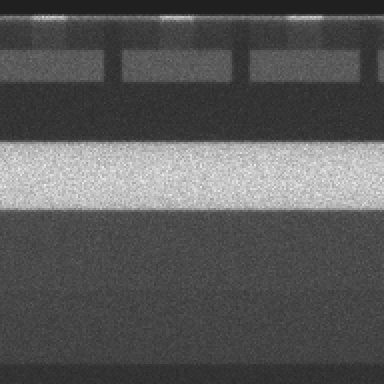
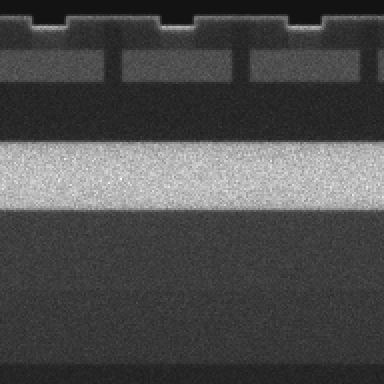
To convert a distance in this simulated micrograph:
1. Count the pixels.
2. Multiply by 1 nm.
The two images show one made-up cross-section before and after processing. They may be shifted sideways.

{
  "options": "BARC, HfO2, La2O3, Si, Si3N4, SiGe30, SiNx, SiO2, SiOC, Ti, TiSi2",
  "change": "removed",
  "material": "SiNx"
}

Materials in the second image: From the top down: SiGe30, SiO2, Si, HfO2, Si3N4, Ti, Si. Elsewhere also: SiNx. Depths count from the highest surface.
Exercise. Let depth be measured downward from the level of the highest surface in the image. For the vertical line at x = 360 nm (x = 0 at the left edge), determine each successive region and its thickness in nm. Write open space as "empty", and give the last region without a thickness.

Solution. Si 126, HfO2 68, Si3N4 80, Ti 74, Si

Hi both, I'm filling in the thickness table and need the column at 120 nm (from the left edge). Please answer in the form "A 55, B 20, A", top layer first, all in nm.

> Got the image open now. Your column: Si 126, HfO2 68, Si3N4 80, Ti 74, Si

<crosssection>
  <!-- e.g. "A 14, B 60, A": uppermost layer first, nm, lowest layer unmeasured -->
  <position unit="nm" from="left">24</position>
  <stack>SiGe30 34, SiO2 32, Si 60, HfO2 68, Si3N4 80, Ti 74, Si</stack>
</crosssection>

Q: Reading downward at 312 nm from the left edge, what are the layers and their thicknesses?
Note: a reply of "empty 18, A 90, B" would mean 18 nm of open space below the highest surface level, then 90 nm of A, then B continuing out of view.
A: empty 10, SiNx 24, SiO2 32, Si 60, HfO2 68, Si3N4 80, Ti 74, Si